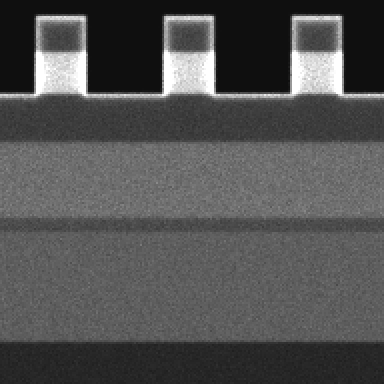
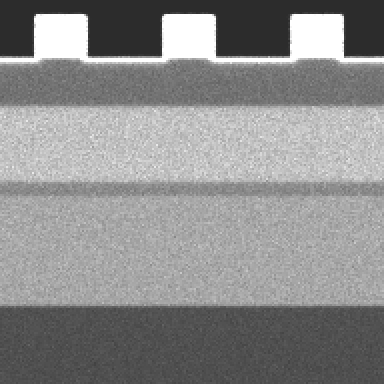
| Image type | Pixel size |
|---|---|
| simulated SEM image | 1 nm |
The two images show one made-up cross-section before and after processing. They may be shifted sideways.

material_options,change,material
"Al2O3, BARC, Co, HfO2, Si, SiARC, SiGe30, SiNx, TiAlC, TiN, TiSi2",removed,SiARC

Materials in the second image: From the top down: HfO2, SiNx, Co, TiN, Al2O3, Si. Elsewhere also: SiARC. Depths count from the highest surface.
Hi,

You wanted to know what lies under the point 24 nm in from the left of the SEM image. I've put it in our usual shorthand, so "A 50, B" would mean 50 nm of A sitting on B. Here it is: empty 42, SiNx 48, Co 76, TiN 14, Al2O3 110, Si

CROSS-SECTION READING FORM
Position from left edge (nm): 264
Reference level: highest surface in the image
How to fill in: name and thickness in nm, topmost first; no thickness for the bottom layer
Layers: empty 42, SiNx 48, Co 76, TiN 14, Al2O3 110, Si